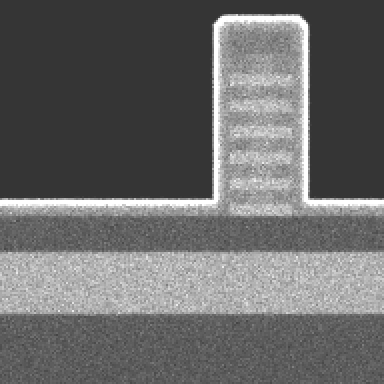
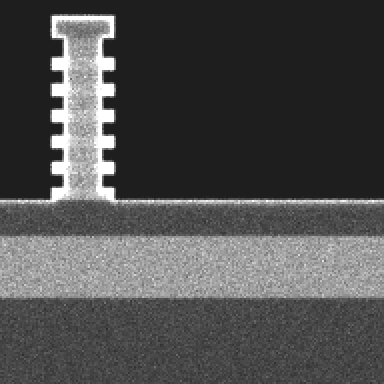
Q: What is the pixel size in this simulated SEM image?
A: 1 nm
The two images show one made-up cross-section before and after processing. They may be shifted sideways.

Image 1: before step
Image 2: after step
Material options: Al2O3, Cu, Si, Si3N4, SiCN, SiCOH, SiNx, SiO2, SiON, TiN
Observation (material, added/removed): Si3N4, removed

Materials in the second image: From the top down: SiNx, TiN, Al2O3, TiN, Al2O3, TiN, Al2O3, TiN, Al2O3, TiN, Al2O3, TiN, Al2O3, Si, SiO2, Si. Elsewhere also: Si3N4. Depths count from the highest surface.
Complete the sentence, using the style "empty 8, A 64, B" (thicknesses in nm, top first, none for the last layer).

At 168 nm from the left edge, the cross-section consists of empty 184, Si 36, SiO2 62, Si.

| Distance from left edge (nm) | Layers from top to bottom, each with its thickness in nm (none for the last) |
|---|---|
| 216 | empty 184, Si 36, SiO2 62, Si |